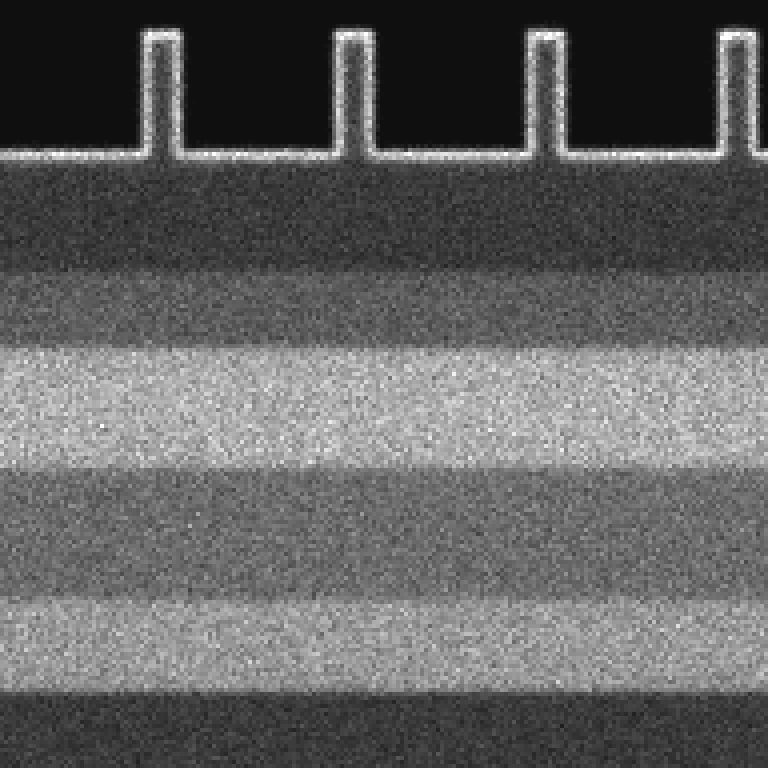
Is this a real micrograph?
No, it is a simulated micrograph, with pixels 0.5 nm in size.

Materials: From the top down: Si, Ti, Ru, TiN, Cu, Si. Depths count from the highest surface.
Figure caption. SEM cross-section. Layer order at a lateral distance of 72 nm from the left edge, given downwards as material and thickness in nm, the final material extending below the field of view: Si 120, Ti 38, Ru 60, TiN 66, Cu 46, Si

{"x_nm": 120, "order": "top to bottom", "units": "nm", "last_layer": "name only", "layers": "empty 60, Si 60, Ti 38, Ru 60, TiN 66, Cu 46, Si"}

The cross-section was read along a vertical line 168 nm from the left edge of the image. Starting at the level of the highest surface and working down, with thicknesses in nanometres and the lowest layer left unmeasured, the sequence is Si 120, Ti 38, Ru 60, TiN 66, Cu 46, Si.